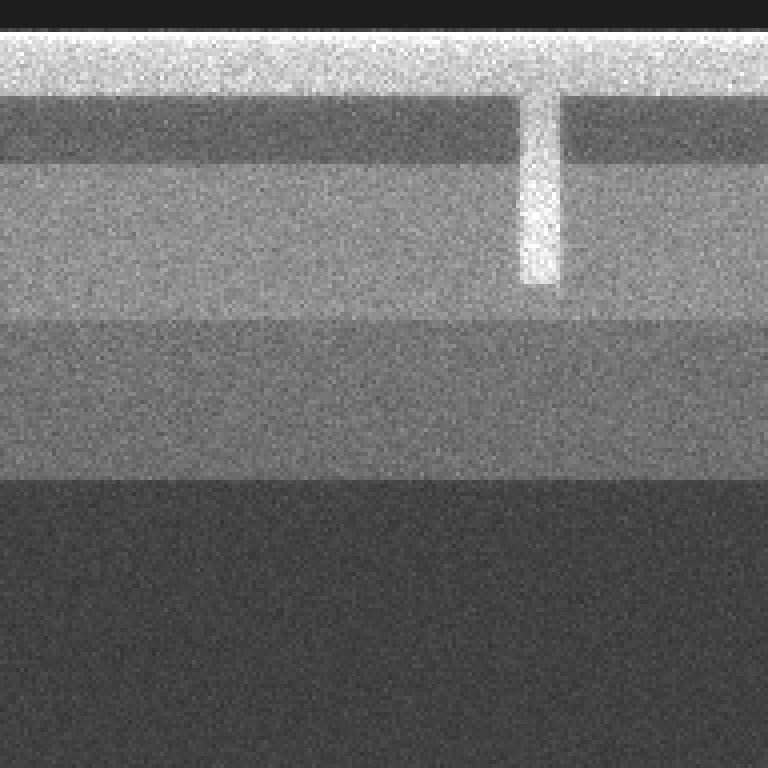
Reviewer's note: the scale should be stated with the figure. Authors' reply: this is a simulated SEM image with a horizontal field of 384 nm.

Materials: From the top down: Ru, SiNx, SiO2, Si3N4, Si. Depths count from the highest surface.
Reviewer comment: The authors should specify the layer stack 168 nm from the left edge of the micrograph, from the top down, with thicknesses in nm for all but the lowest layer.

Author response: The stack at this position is Ru 32, SiNx 34, SiO2 78, Si3N4 80, Si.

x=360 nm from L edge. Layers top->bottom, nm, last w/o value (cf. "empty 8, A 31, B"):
Ru 32, SiNx 34, SiO2 78, Si3N4 80, Si